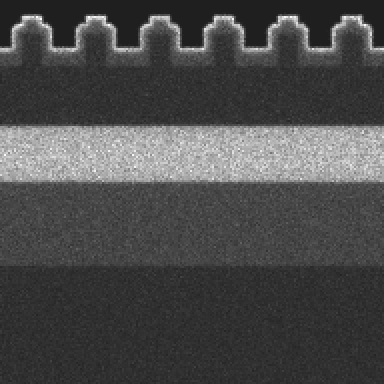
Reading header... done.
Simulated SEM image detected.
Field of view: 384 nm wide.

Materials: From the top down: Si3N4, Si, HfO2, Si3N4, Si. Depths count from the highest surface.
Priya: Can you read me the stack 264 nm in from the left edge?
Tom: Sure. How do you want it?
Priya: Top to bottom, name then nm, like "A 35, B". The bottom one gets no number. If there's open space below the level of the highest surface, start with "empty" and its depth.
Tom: empty 32, Si3N4 18, Si 60, HfO2 56, Si3N4 84, Si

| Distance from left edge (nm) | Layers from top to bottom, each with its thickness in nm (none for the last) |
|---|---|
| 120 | empty 32, Si3N4 18, Si 60, HfO2 56, Si3N4 84, Si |